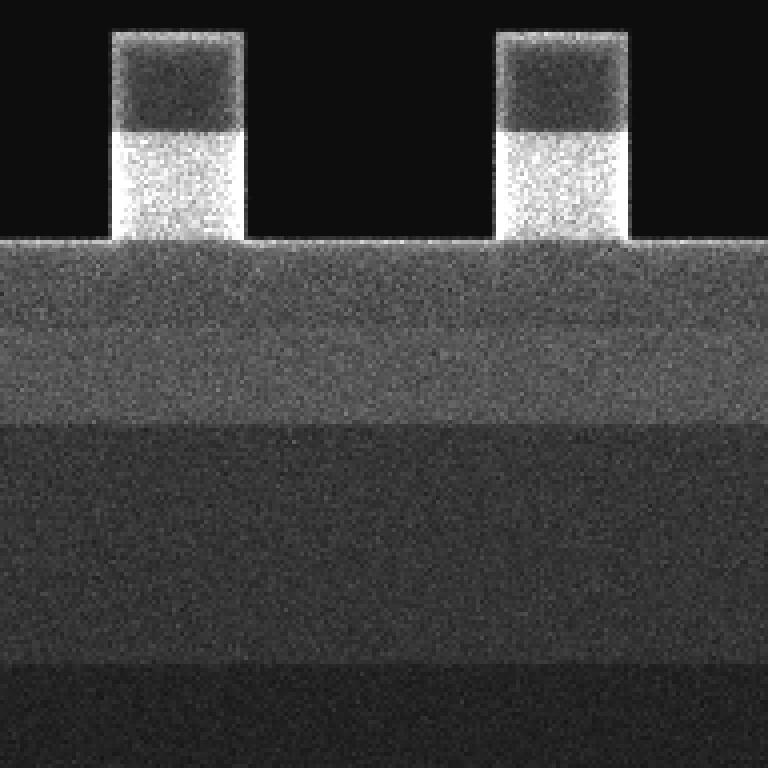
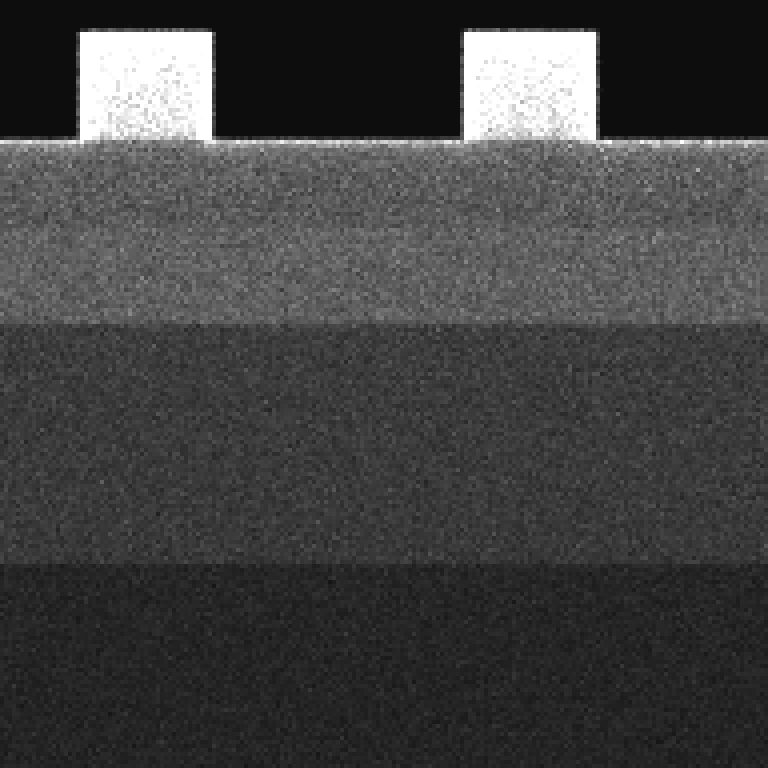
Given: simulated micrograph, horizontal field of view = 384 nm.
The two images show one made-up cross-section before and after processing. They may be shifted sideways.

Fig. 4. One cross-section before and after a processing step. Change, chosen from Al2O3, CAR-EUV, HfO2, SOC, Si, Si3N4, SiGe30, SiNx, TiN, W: SOC removed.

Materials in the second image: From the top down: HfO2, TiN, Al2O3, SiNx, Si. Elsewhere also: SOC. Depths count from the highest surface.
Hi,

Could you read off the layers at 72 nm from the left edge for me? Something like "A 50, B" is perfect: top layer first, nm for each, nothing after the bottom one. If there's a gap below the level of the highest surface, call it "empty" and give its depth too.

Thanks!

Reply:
HfO2 54, TiN 44, Al2O3 48, SiNx 120, Si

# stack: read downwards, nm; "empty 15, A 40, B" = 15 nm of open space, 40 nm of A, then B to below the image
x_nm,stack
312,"empty 54, TiN 44, Al2O3 48, SiNx 120, Si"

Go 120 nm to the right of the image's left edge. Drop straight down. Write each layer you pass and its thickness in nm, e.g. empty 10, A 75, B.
empty 54, TiN 44, Al2O3 48, SiNx 120, Si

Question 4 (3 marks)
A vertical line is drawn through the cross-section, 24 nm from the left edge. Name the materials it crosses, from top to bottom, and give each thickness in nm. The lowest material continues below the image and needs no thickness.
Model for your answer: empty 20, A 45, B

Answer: empty 54, TiN 44, Al2O3 48, SiNx 120, Si